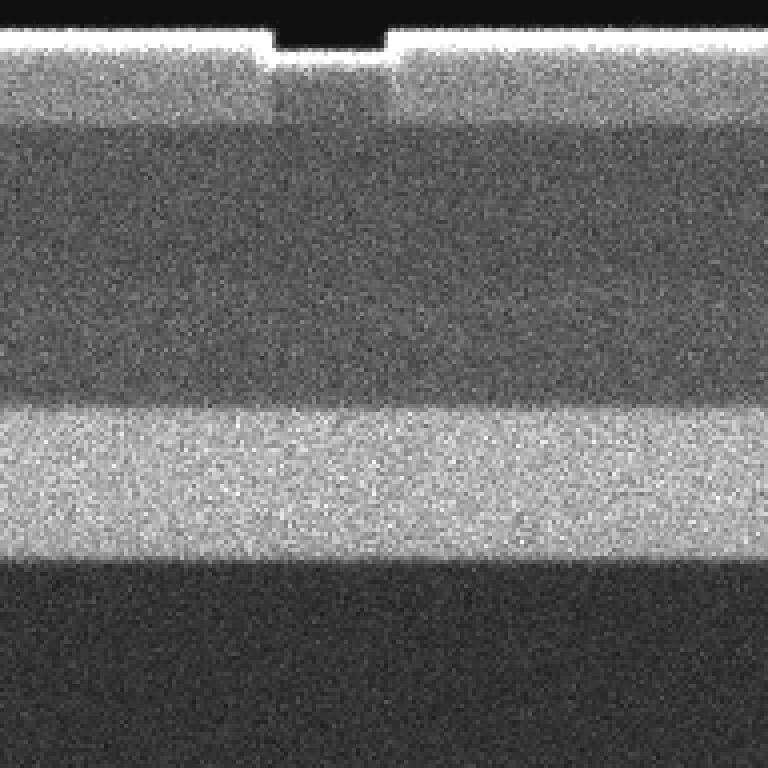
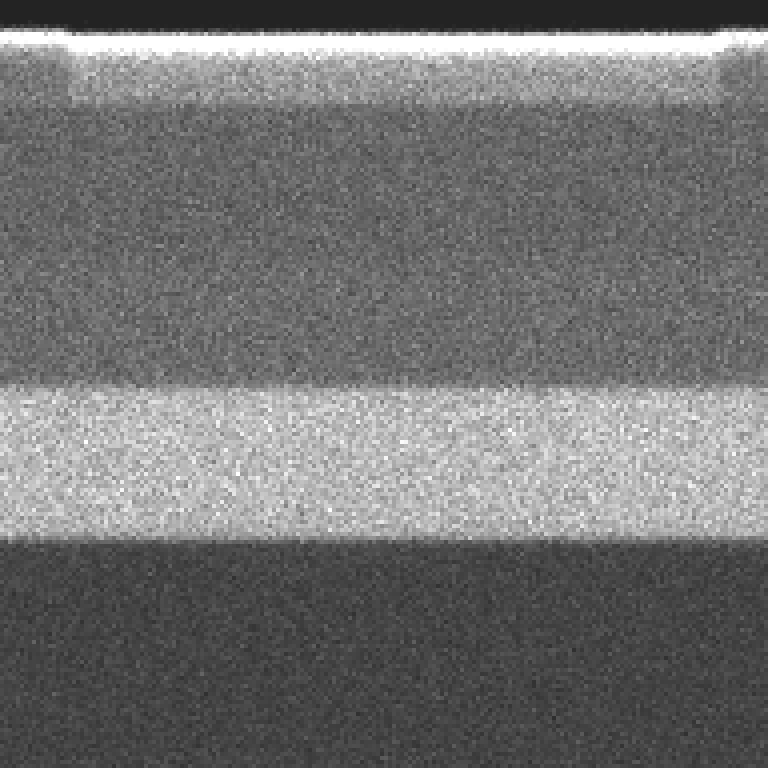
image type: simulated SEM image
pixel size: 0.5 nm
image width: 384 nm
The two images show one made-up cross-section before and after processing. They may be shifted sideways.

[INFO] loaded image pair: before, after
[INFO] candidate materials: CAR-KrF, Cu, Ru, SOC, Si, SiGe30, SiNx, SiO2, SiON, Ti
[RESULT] removed SiO2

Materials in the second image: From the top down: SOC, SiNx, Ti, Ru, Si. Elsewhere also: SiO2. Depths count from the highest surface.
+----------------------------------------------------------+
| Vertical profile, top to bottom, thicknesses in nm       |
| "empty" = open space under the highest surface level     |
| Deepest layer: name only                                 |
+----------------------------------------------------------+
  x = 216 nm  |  empty 2, SiO2 34, SiNx 78, Ti 64, Ru 76, Si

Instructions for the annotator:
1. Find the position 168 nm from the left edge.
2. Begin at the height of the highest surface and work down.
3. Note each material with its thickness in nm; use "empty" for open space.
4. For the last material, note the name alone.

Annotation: empty 2, SiO2 34, SiNx 78, Ti 64, Ru 76, Si